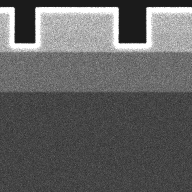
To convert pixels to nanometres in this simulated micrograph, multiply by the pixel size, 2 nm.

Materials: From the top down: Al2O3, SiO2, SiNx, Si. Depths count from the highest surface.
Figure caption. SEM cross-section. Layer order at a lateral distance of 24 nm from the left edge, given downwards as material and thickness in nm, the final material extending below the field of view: Al2O3 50, SiO2 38, SiNx 80, Si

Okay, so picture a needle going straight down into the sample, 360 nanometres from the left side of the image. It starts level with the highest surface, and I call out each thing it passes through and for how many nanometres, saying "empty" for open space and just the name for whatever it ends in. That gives Al2O3 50, SiO2 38, SiNx 80, Si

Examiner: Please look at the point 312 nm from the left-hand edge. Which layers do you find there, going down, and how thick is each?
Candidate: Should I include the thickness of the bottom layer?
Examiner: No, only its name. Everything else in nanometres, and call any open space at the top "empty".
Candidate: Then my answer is Al2O3 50, SiO2 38, SiNx 80, Si